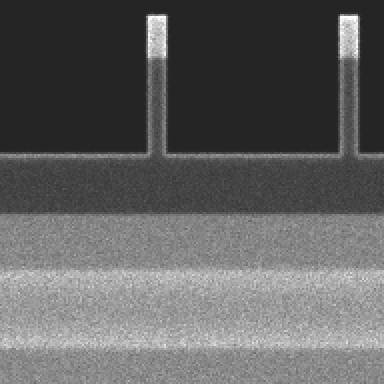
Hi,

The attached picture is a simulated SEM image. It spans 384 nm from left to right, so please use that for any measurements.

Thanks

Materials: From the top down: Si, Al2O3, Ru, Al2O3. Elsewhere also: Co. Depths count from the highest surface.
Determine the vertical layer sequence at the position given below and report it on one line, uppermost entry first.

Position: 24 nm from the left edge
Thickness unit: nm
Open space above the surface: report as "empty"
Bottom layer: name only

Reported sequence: empty 138, Si 60, Al2O3 56, Ru 78, Al2O3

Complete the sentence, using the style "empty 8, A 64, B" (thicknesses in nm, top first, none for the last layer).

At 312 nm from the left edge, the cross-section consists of empty 138, Si 60, Al2O3 56, Ru 78, Al2O3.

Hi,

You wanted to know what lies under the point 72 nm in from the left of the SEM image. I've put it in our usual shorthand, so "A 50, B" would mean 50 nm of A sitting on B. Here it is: empty 138, Si 60, Al2O3 56, Ru 78, Al2O3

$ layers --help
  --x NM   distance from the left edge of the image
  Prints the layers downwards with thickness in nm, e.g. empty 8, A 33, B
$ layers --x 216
empty 138, Si 60, Al2O3 56, Ru 78, Al2O3